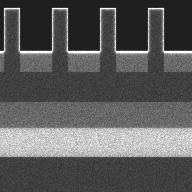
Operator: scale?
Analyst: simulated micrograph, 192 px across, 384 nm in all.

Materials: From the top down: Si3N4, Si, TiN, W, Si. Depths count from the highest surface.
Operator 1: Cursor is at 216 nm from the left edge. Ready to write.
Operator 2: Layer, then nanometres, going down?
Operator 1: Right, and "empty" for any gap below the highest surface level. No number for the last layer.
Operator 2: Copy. Si 188, TiN 52, W 58, Si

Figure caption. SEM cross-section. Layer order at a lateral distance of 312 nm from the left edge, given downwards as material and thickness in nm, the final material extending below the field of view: Si 188, TiN 52, W 58, Si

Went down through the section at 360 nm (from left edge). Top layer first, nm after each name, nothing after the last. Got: empty 86, Si3N4 42, Si 60, TiN 52, W 58, Si